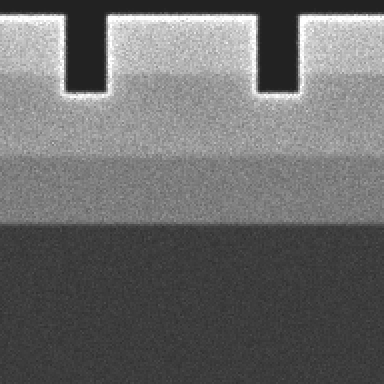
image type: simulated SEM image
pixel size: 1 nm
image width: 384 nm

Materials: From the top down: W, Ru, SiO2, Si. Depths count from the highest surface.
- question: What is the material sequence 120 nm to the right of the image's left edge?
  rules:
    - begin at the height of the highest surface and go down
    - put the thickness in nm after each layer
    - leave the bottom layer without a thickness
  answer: W 58, Ru 82, SiO2 68, Si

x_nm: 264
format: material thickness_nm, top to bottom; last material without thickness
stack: empty 78, Ru 62, SiO2 68, Si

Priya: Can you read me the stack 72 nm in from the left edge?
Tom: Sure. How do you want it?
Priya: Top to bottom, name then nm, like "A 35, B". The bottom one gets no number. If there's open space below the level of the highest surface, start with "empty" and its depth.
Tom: empty 78, Ru 62, SiO2 68, Si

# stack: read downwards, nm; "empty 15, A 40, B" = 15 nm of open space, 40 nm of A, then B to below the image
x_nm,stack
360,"W 58, Ru 82, SiO2 68, Si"